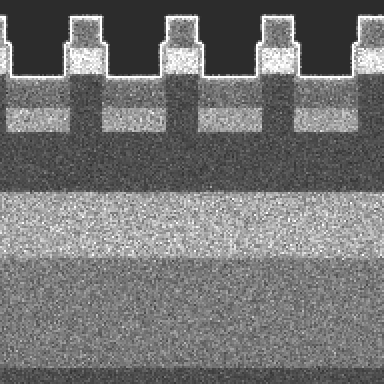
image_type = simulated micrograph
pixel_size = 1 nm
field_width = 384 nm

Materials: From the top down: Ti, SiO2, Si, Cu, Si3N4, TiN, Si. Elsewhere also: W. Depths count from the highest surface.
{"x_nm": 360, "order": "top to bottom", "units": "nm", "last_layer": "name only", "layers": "Ti 32, W 26, Si 118, Cu 66, Si3N4 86, TiN 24, Si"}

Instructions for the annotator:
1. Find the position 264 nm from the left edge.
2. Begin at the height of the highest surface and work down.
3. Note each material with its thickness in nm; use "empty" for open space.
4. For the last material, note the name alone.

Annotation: Ti 32, W 26, Si 118, Cu 66, Si3N4 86, TiN 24, Si